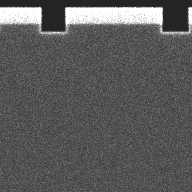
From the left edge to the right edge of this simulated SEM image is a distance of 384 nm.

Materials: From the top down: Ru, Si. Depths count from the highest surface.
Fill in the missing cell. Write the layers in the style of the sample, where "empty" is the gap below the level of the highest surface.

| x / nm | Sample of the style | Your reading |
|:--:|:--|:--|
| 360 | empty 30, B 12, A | empty 48, Si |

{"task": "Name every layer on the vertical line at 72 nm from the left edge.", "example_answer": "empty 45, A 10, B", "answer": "Ru 32, Si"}